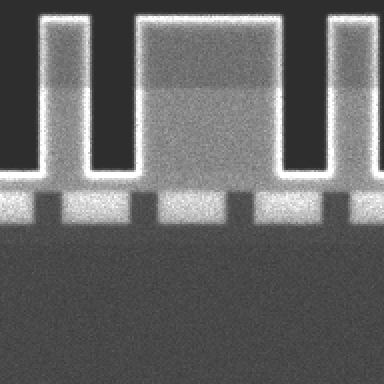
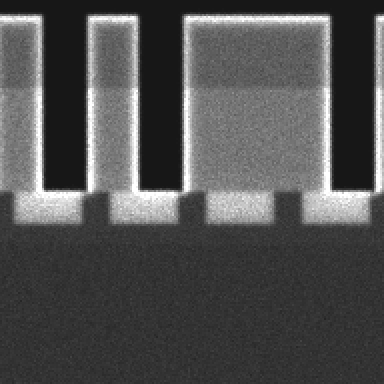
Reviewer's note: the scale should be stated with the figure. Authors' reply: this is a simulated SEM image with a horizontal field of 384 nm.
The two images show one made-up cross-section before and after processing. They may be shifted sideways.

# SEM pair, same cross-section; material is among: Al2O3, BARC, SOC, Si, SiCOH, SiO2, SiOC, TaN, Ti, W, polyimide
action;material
removed;Al2O3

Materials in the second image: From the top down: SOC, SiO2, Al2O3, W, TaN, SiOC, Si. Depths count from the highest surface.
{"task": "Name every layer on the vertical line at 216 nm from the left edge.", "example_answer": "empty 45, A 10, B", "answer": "SOC 72, SiO2 84, Al2O3 20, W 26, TaN 6, SiOC 20, Si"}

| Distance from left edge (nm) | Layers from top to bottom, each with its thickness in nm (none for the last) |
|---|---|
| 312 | SOC 72, SiO2 84, Al2O3 20, W 26, TaN 6, SiOC 20, Si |